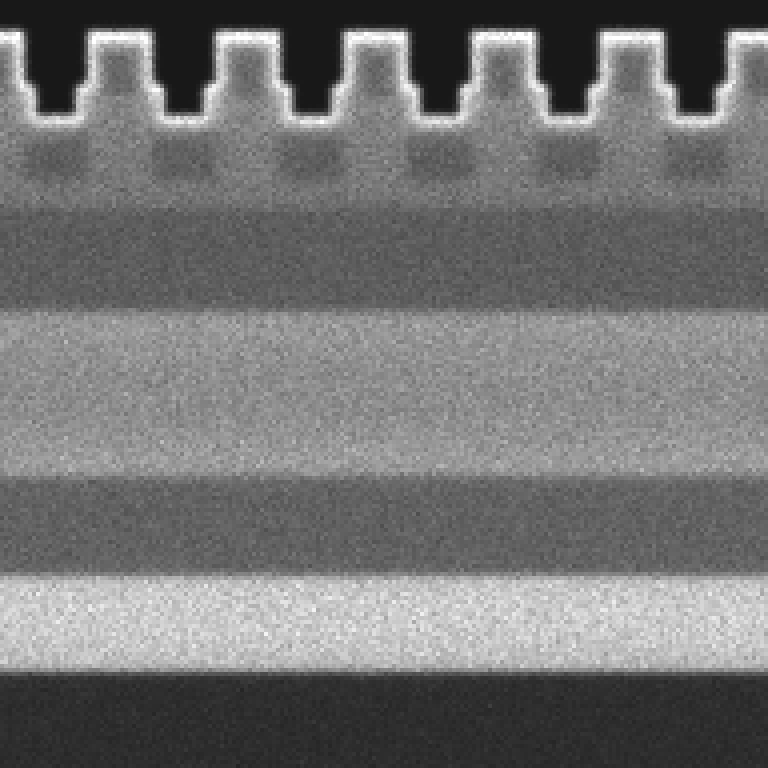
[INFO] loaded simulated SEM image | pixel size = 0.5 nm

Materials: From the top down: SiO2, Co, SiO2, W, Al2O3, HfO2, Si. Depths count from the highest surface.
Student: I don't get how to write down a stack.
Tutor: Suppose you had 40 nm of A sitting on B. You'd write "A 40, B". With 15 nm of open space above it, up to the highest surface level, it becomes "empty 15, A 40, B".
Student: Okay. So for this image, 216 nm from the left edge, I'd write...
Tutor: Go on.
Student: empty 42, SiO2 32, Co 14, SiO2 52, W 82, Al2O3 50, HfO2 48, Si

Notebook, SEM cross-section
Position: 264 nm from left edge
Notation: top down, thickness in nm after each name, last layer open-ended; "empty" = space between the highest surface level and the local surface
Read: SiO2 32, Co 56, SiO2 52, W 82, Al2O3 50, HfO2 48, Si